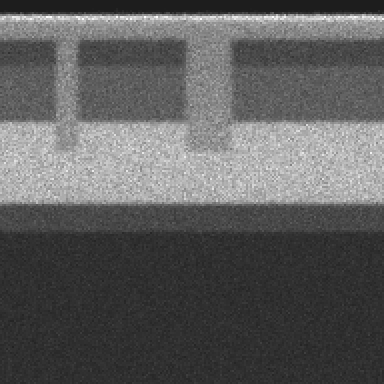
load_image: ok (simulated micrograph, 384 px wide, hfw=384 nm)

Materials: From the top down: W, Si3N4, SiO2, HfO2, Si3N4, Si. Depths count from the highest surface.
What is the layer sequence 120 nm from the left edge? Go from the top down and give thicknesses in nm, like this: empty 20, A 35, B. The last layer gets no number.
W 24, Si3N4 26, SiO2 56, HfO2 82, Si3N4 28, Si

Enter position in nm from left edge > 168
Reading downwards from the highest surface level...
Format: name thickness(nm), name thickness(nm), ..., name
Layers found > W 24, Si3N4 26, SiO2 56, HfO2 82, Si3N4 28, Si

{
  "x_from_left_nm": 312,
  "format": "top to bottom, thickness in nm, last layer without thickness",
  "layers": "W 24, Si3N4 26, SiO2 56, HfO2 82, Si3N4 28, Si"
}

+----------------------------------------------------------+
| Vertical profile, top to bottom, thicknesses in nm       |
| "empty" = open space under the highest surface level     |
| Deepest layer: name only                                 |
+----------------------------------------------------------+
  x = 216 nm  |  W 136, HfO2 52, Si3N4 28, Si